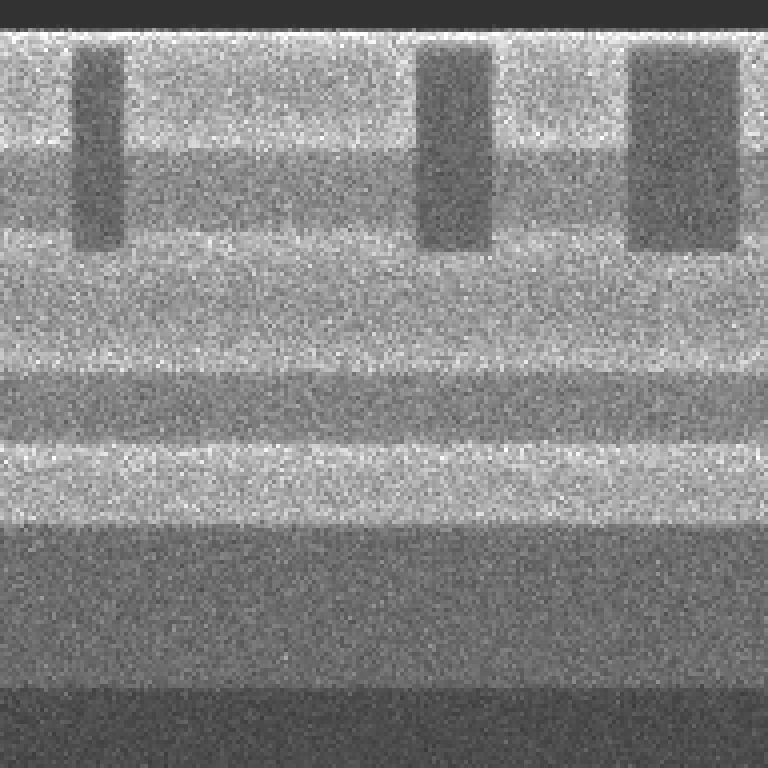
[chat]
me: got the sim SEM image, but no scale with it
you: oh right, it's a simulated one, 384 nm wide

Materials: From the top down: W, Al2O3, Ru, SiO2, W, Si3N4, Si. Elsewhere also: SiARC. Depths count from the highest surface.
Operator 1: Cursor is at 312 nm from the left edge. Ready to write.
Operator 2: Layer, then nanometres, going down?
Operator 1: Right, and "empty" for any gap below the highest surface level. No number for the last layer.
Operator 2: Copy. W 58, Al2O3 42, Ru 70, SiO2 36, W 40, Si3N4 82, Si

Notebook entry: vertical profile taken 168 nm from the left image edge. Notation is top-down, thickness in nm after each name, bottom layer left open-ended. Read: W 58, Al2O3 42, Ru 70, SiO2 36, W 40, Si3N4 82, Si